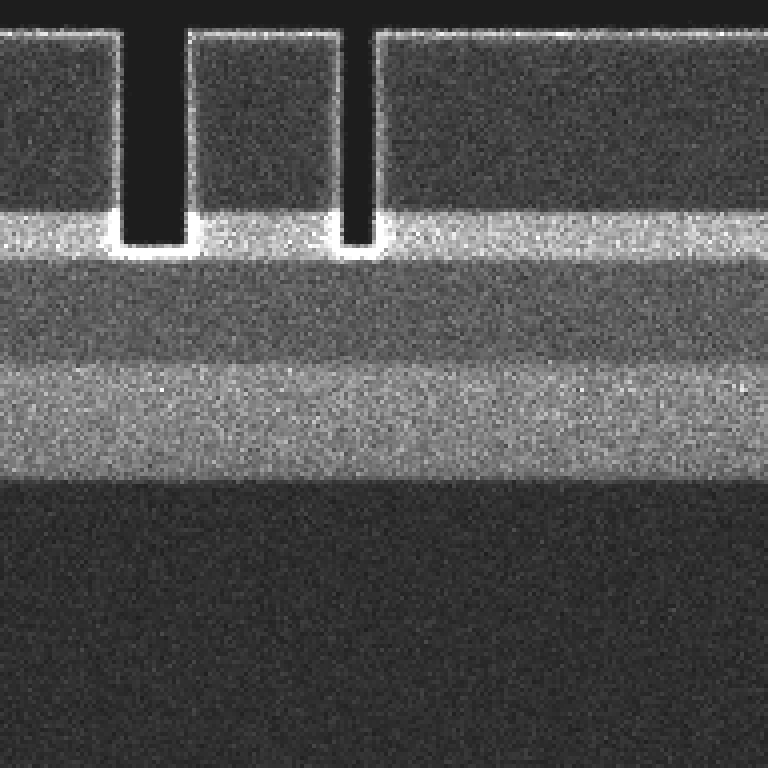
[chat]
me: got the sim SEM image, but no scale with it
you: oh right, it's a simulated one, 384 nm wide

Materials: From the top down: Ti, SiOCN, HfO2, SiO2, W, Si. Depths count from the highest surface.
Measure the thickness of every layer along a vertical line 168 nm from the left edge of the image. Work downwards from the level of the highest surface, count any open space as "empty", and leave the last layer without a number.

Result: Ti 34, SiOCN 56, HfO2 24, SiO2 52, W 58, Si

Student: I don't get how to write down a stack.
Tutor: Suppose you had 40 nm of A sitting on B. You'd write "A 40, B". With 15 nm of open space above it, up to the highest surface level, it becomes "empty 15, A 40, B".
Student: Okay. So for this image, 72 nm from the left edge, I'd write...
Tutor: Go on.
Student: empty 108, HfO2 6, SiO2 52, W 58, Si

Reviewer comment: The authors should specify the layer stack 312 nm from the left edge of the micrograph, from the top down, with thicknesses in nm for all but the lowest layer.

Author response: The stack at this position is Ti 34, SiOCN 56, HfO2 24, SiO2 52, W 58, Si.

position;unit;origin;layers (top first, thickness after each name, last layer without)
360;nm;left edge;Ti 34, SiOCN 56, HfO2 24, SiO2 52, W 58, Si